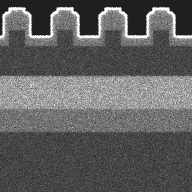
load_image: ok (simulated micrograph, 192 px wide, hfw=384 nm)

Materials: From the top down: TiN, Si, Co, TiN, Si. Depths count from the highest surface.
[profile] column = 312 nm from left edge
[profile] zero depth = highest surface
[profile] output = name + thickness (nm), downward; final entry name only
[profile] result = TiN 44, Si 92, Co 66, TiN 46, Si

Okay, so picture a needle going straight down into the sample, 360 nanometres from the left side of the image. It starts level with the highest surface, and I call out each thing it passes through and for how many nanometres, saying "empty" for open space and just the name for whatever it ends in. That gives empty 56, TiN 20, Si 60, Co 66, TiN 46, Si